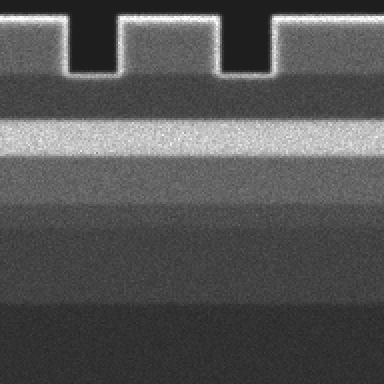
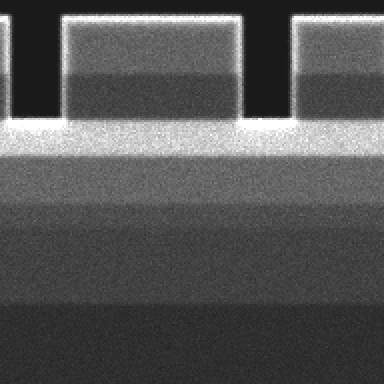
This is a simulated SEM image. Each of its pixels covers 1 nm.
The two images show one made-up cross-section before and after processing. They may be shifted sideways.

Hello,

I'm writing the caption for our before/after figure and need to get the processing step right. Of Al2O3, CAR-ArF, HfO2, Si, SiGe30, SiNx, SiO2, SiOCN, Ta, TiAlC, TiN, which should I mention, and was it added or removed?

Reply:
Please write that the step removed SiNx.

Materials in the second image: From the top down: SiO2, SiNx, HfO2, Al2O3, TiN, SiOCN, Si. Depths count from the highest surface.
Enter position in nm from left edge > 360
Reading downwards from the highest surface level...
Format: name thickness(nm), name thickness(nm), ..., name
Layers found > SiO2 58, SiNx 46, HfO2 36, Al2O3 48, TiN 24, SiOCN 76, Si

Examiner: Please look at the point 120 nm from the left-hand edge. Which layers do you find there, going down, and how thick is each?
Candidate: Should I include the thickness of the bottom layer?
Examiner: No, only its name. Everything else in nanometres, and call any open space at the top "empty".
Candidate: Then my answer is SiO2 58, SiNx 46, HfO2 36, Al2O3 48, TiN 24, SiOCN 76, Si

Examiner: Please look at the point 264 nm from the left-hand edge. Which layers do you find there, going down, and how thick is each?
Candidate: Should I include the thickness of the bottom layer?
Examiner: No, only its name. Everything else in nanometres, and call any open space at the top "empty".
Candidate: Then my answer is empty 104, HfO2 36, Al2O3 48, TiN 24, SiOCN 76, Si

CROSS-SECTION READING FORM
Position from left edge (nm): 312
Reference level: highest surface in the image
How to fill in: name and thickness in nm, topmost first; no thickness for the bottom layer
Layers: SiO2 58, SiNx 46, HfO2 36, Al2O3 48, TiN 24, SiOCN 76, Si